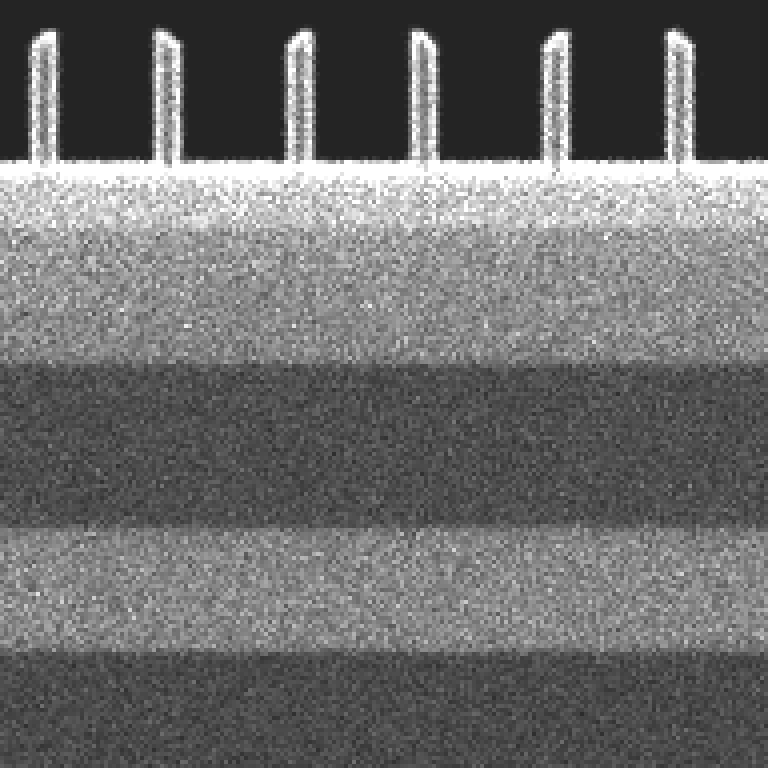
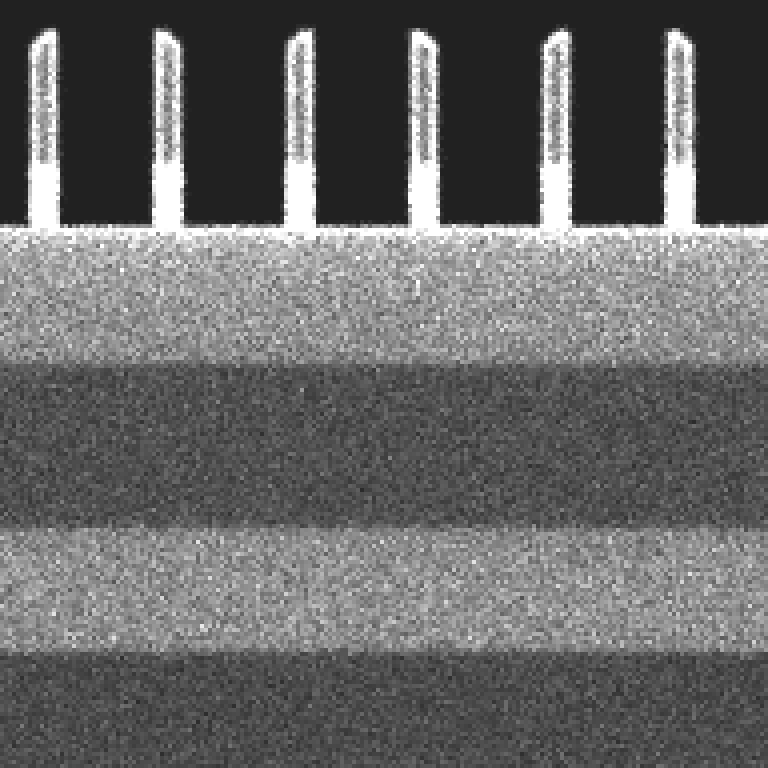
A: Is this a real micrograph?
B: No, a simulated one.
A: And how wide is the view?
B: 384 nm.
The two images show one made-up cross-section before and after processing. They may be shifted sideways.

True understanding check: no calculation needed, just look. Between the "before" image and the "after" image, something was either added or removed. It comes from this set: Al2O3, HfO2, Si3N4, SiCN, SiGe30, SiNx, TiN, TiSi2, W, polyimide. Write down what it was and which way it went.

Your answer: HfO2 (removed)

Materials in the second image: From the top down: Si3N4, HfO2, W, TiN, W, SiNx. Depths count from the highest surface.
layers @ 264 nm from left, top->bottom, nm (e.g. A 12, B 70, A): empty 98, W 68, TiN 82, W 62, SiNx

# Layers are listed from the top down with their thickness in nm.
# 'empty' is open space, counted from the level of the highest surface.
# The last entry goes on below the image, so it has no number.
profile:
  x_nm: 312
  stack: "empty 98, W 68, TiN 82, W 62, SiNx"